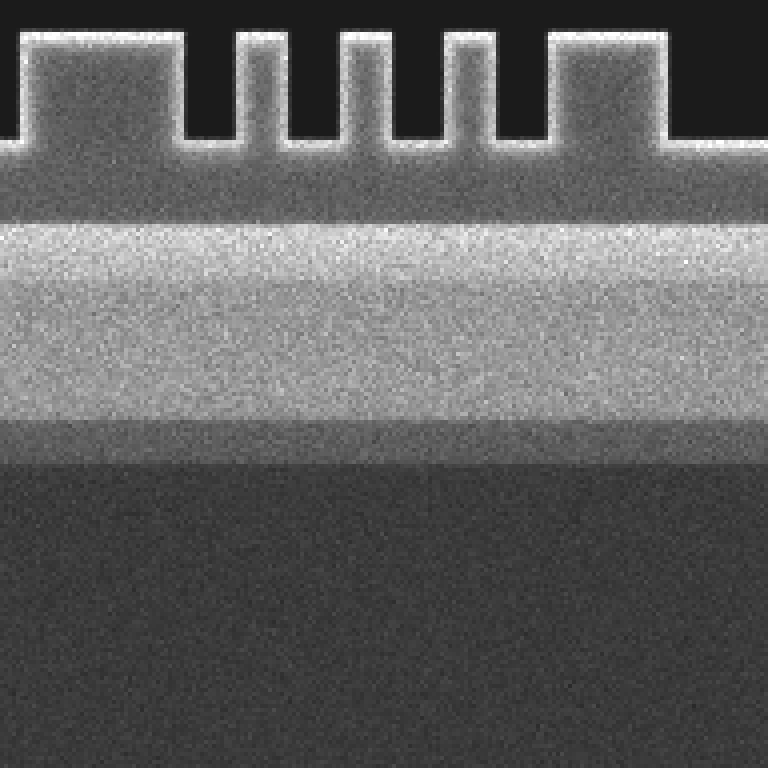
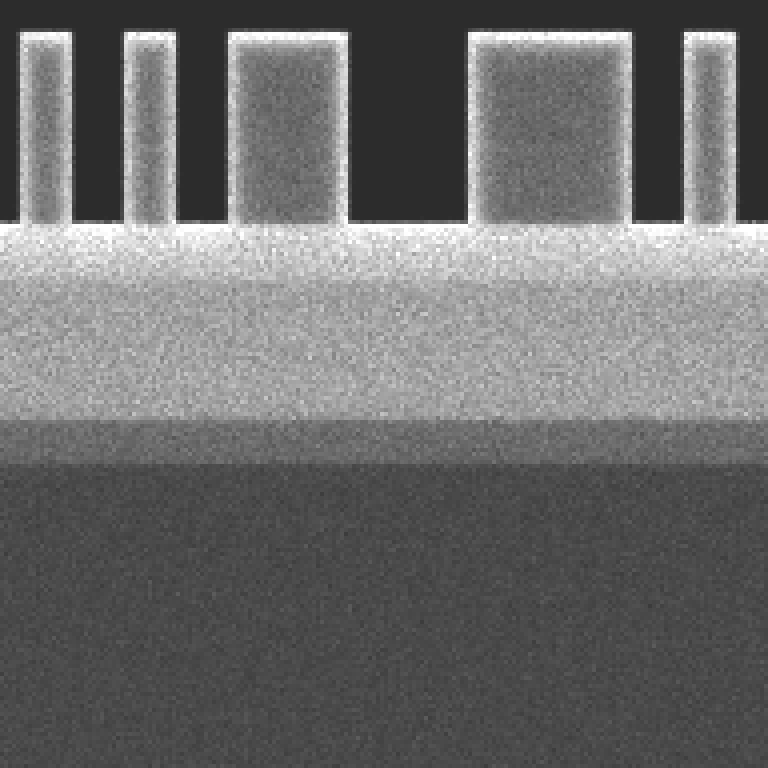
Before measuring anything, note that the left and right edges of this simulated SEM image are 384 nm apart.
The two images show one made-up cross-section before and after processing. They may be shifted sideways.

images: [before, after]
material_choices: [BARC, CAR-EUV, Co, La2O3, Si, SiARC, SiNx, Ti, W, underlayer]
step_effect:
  removed: underlayer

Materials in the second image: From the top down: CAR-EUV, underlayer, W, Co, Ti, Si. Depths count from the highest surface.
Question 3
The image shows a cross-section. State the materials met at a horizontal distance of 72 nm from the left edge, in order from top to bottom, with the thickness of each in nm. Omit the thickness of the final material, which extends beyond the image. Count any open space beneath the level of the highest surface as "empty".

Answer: CAR-EUV 54, underlayer 42, W 28, Co 70, Ti 22, Si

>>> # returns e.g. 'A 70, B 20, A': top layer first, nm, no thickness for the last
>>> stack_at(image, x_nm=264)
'CAR-EUV 54, underlayer 42, W 28, Co 70, Ti 22, Si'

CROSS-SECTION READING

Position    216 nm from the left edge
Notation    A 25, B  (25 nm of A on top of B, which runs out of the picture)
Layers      empty 96, W 28, Co 70, Ti 22, Si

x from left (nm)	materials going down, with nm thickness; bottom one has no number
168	CAR-EUV 54, underlayer 42, W 28, Co 70, Ti 22, Si